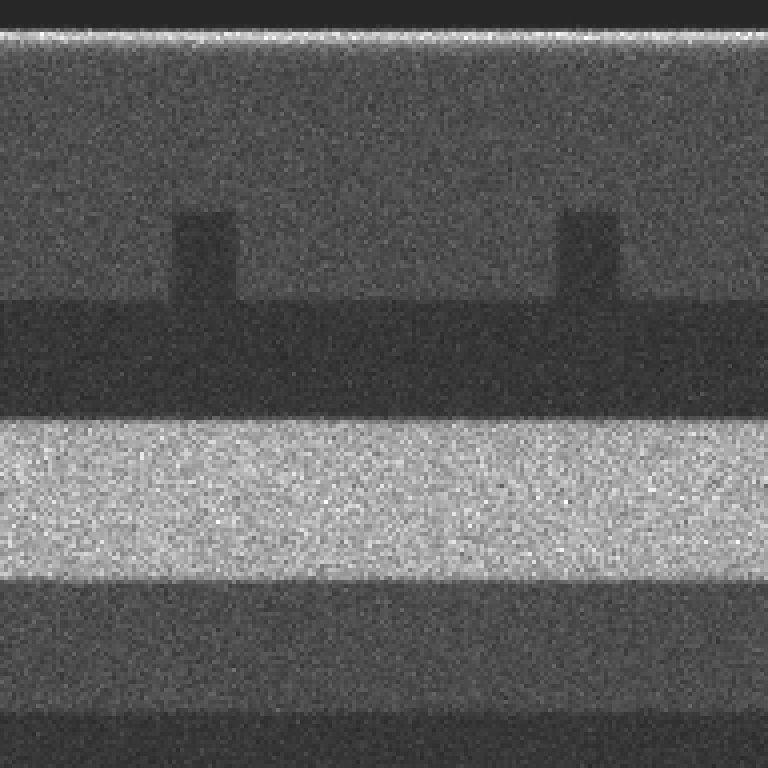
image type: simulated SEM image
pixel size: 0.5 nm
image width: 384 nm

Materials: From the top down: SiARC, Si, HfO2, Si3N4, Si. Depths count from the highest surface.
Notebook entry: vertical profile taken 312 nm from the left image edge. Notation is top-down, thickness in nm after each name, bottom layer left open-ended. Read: SiARC 134, Si 60, HfO2 80, Si3N4 66, Si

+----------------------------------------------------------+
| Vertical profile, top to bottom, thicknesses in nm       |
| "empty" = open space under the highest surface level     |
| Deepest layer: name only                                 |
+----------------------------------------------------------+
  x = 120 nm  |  SiARC 134, Si 60, HfO2 80, Si3N4 66, Si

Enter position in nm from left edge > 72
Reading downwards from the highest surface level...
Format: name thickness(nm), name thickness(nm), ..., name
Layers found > SiARC 134, Si 60, HfO2 80, Si3N4 66, Si